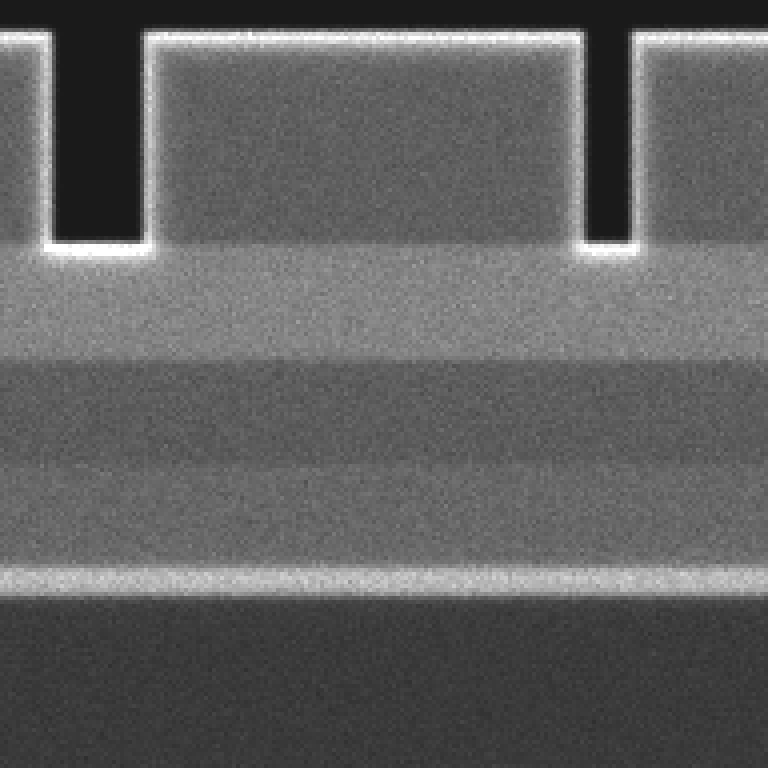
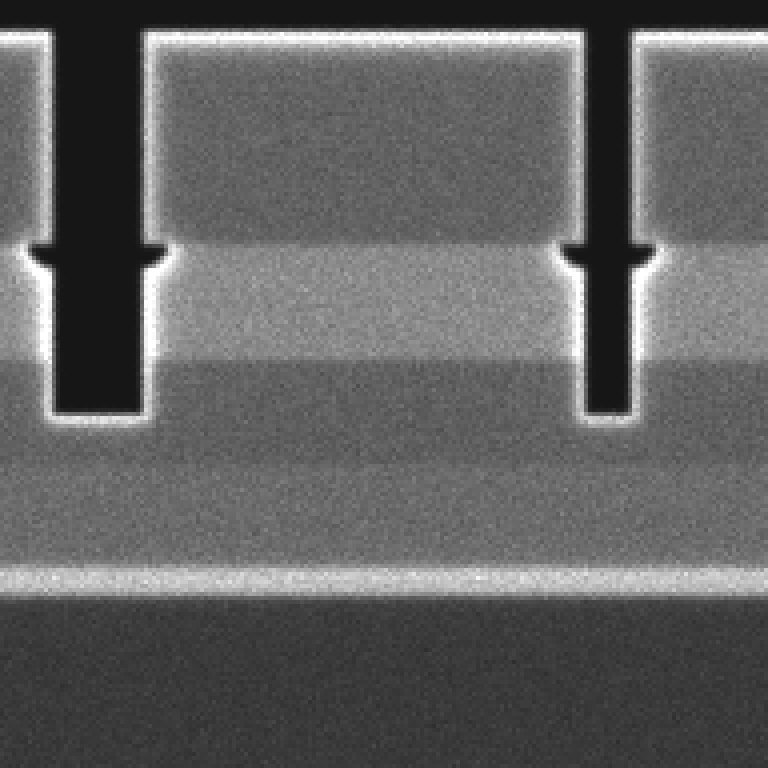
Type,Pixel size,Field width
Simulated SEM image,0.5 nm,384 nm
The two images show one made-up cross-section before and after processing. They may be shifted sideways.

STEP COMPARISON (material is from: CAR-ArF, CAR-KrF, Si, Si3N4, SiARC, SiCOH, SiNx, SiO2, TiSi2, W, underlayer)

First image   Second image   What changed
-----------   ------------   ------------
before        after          SiNx and SiO2, removed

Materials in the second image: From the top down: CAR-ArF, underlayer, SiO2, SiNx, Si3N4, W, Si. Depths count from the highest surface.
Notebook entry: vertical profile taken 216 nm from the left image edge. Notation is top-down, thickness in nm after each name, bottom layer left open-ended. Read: CAR-ArF 58, underlayer 48, SiO2 58, SiNx 52, Si3N4 52, W 14, Si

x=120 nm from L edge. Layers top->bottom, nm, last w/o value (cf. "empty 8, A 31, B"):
CAR-ArF 58, underlayer 48, SiO2 58, SiNx 52, Si3N4 52, W 14, Si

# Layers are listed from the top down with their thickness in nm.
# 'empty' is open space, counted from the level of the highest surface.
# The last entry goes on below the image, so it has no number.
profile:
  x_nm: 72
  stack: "CAR-ArF 58, underlayer 48, empty 12, SiO2 46, SiNx 52, Si3N4 52, W 14, Si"